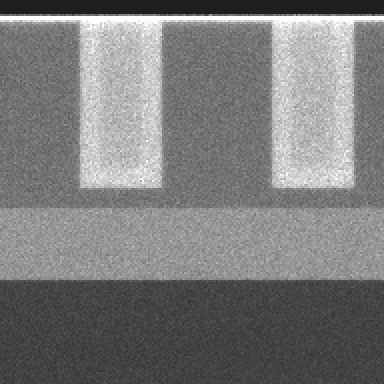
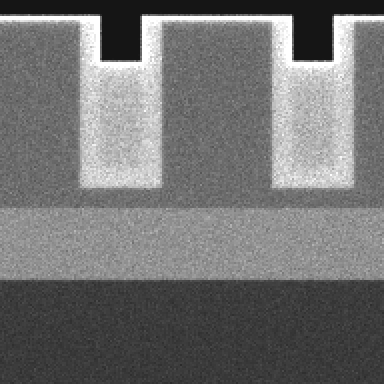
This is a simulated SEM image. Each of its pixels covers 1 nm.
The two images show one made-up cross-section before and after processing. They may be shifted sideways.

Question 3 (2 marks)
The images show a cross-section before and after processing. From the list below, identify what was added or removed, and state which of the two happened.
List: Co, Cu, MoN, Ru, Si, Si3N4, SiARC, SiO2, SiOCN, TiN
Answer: Co was removed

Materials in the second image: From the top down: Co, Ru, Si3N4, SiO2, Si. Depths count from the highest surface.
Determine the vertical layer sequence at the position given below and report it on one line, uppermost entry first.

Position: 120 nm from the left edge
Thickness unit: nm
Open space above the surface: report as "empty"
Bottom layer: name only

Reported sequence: empty 46, Co 106, Ru 20, Si3N4 20, SiO2 72, Si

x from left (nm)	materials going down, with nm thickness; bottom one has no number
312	empty 46, Co 106, Ru 20, Si3N4 20, SiO2 72, Si